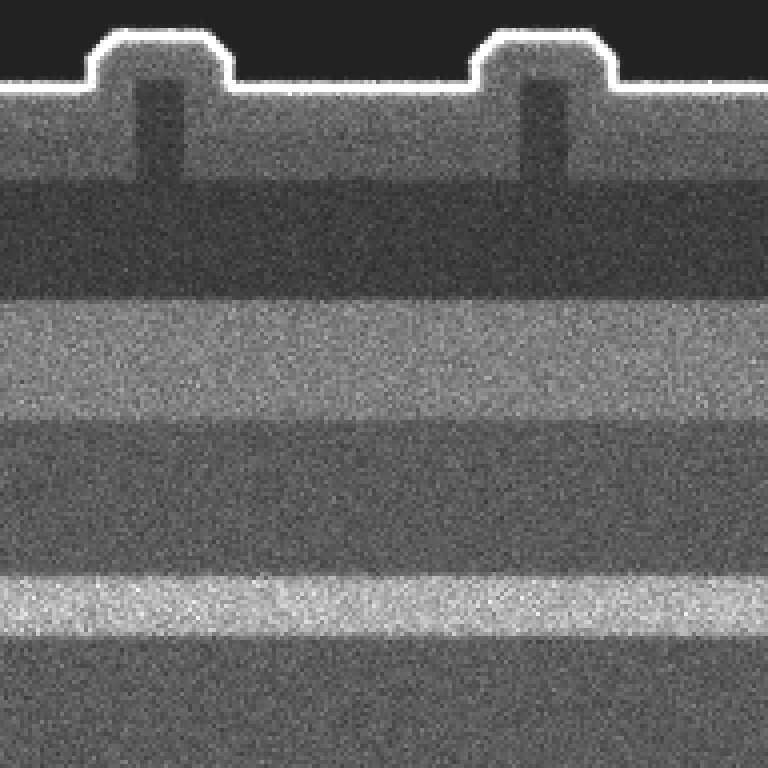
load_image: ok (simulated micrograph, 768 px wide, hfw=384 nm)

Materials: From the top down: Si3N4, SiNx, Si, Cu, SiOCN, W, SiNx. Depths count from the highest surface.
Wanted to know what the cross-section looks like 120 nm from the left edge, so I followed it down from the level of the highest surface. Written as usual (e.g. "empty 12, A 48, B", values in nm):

empty 26, Si3N4 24, SiNx 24, Si 60, Cu 60, SiOCN 78, W 30, SiNx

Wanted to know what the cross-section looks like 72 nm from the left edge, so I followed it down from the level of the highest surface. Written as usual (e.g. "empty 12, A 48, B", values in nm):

Si3N4 24, Si 110, Cu 60, SiOCN 78, W 30, SiNx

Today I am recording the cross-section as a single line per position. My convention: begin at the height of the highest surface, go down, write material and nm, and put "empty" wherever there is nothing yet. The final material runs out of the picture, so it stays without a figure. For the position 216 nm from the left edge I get empty 26, Si3N4 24, SiNx 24, Si 60, Cu 60, SiOCN 78, W 30, SiNx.